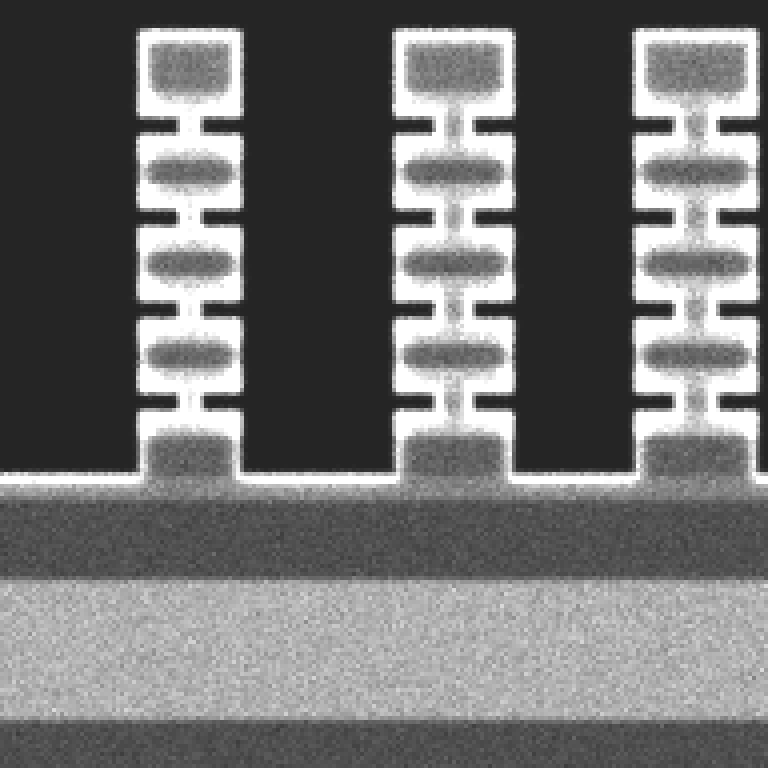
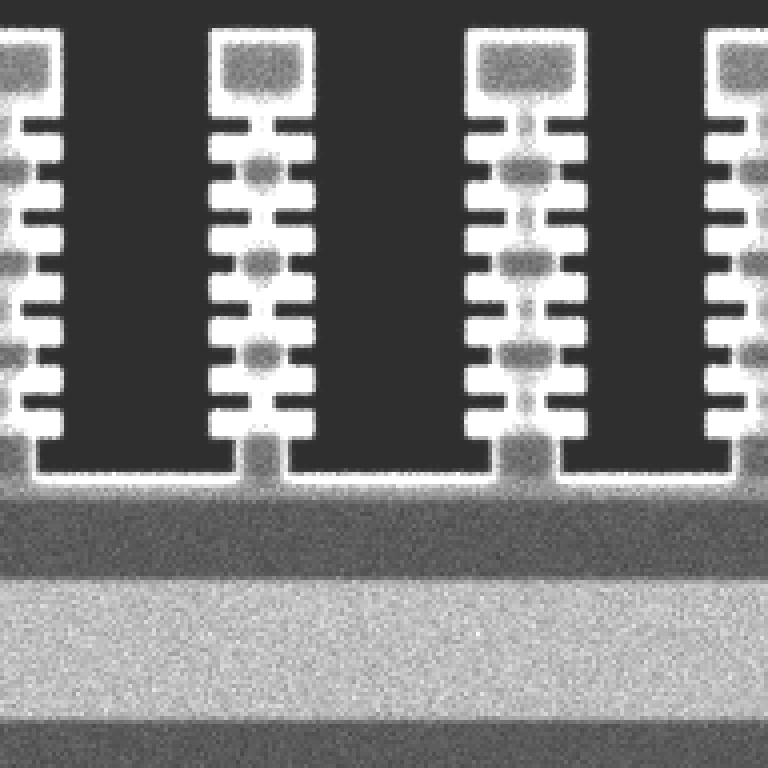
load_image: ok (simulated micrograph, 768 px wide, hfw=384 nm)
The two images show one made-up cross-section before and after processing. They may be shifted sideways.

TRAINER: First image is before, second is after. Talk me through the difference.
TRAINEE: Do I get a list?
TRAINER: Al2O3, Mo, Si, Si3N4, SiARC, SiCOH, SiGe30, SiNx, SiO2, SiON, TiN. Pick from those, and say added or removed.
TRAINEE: removed: SiGe30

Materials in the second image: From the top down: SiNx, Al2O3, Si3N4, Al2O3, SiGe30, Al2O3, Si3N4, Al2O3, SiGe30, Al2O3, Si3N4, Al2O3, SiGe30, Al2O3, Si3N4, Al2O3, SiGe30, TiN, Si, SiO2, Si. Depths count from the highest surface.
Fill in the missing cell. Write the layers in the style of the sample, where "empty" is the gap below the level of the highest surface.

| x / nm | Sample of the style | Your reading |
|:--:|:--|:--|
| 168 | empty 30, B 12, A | empty 222, TiN 12, Si 40, SiO2 70, Si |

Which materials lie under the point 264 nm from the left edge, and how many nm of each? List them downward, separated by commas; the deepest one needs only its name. SiNx 30, Al2O3 12, Si3N4 10, Al2O3 12, SiGe30 12, Al2O3 12, Si3N4 10, Al2O3 12, SiGe30 12, Al2O3 12, Si3N4 10, Al2O3 12, SiGe30 12, Al2O3 12, Si3N4 10, Al2O3 12, SiGe30 20, TiN 12, Si 40, SiO2 70, Si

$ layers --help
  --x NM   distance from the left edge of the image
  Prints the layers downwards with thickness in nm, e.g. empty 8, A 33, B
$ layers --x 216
empty 222, TiN 12, Si 40, SiO2 70, Si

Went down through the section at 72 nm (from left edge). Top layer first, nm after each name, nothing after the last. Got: empty 222, TiN 12, Si 40, SiO2 70, Si